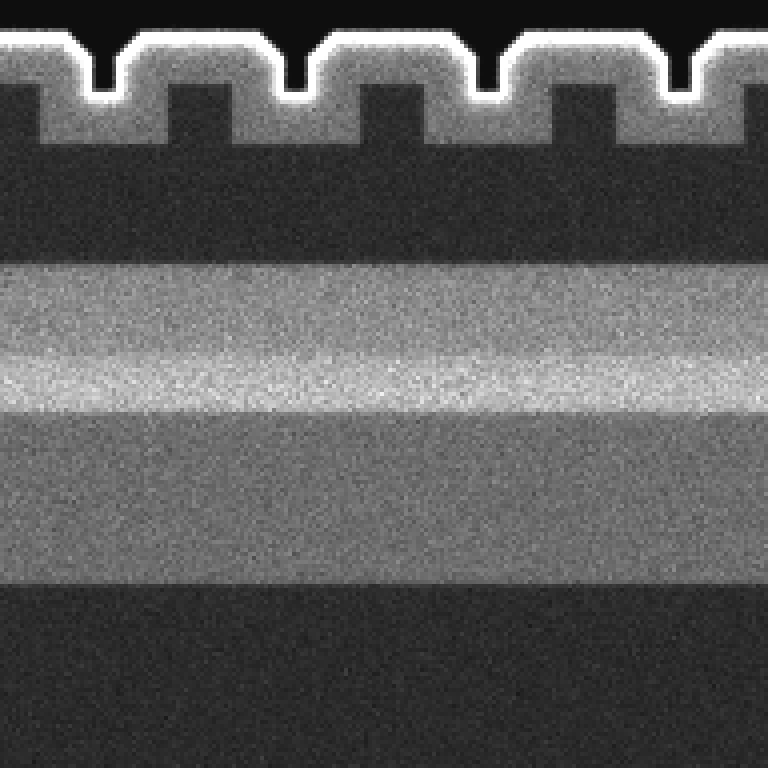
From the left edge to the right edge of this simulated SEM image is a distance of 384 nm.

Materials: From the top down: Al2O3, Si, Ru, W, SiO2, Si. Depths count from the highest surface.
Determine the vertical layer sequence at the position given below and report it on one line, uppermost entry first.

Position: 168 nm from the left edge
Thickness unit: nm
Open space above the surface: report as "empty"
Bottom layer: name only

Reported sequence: Al2O3 56, Si 60, Ru 46, W 28, SiO2 86, Si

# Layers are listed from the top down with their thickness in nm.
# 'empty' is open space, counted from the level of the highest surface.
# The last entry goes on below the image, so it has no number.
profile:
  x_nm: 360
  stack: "Al2O3 56, Si 60, Ru 46, W 28, SiO2 86, Si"